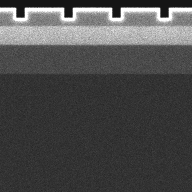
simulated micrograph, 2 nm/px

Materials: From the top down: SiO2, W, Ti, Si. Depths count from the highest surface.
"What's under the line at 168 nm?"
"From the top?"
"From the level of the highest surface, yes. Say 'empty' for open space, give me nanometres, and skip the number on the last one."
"SiO2 36, W 38, Ti 58, Si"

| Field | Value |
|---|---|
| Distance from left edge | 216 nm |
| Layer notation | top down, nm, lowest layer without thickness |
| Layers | SiO2 36, W 38, Ti 58, Si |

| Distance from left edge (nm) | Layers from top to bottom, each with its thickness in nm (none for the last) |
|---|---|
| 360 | SiO2 36, W 38, Ti 58, Si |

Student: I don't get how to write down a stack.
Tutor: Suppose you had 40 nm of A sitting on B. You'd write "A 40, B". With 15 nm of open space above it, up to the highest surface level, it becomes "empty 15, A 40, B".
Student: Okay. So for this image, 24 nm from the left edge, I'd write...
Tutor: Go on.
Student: SiO2 36, W 38, Ti 58, Si